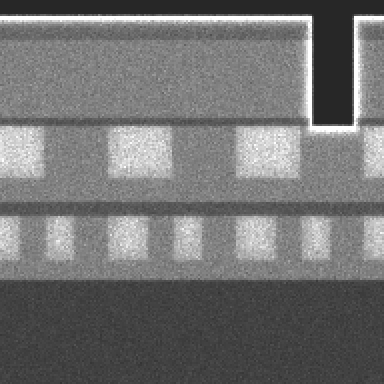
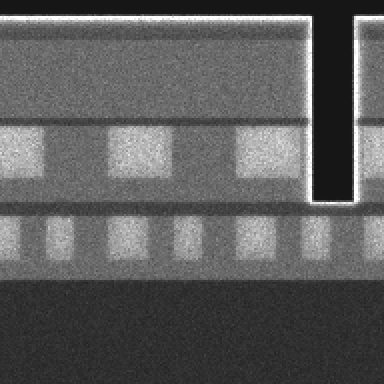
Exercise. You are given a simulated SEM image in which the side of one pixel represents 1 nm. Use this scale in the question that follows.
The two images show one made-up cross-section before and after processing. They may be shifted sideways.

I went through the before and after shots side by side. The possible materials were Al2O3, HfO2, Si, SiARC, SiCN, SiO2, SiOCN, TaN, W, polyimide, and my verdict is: removed, SiO2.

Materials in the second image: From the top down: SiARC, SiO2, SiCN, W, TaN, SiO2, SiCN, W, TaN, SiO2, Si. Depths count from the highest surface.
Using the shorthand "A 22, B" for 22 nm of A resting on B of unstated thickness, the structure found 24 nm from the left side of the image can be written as SiARC 24, SiO2 78, SiCN 8, W 42, TaN 10, SiO2 24, SiCN 14, SiO2 64, Si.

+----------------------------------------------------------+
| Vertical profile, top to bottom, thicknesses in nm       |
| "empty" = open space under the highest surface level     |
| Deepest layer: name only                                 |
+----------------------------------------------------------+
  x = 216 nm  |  SiARC 24, SiO2 78, SiCN 8, SiO2 76, SiCN 14, SiO2 64, Si